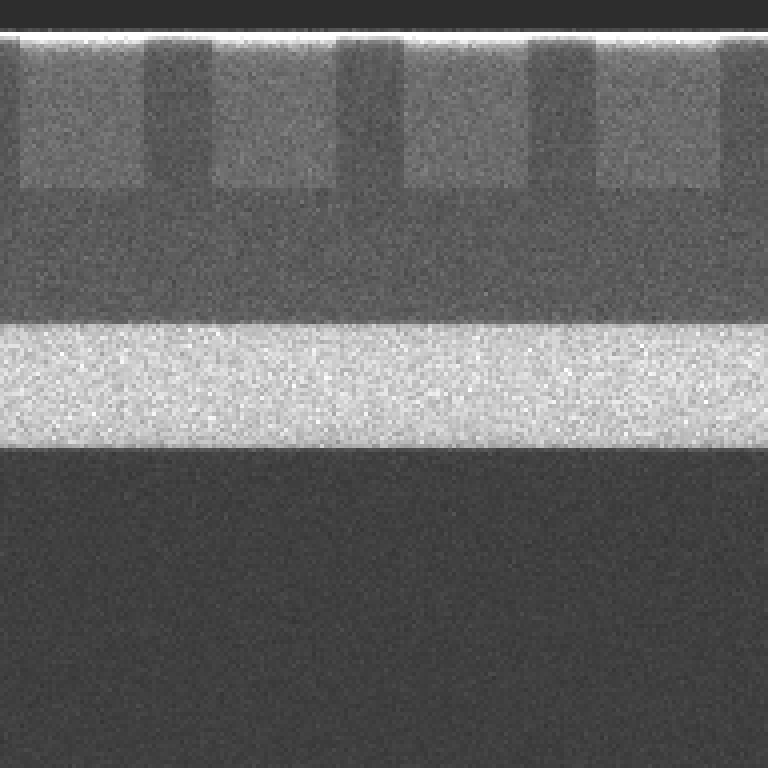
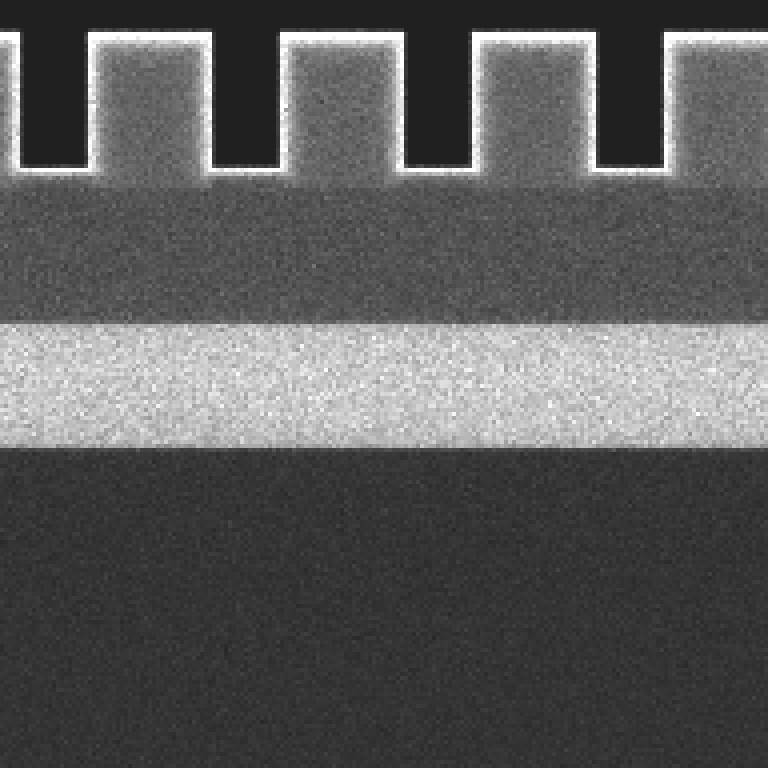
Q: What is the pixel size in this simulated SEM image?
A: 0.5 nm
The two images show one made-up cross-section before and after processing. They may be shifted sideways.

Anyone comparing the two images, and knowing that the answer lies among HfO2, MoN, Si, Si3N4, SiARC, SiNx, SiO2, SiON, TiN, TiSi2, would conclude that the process removed Si3N4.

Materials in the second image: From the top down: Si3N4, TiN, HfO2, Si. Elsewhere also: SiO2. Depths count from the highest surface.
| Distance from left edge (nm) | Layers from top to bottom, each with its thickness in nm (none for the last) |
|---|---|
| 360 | SiO2 78, TiN 68, HfO2 62, Si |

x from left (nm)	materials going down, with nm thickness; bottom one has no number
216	empty 68, Si3N4 24, TiN 54, HfO2 62, Si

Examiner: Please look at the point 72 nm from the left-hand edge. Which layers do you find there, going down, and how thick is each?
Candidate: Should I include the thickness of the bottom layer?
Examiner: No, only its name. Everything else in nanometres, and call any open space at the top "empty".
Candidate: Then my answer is SiO2 78, TiN 68, HfO2 62, Si